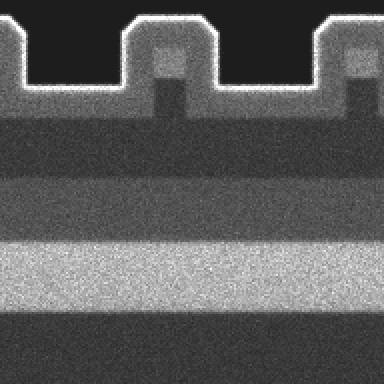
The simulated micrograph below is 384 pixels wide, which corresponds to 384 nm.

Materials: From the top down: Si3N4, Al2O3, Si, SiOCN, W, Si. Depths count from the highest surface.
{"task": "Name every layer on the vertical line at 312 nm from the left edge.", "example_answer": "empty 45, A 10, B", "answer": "empty 70, Si3N4 32, Si 60, SiOCN 64, W 70, Si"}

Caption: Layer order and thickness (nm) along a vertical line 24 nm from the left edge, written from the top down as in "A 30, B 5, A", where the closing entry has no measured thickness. empty 16, Si3N4 86, Si 60, SiOCN 64, W 70, Si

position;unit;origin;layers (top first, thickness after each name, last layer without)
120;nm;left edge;empty 70, Si3N4 32, Si 60, SiOCN 64, W 70, Si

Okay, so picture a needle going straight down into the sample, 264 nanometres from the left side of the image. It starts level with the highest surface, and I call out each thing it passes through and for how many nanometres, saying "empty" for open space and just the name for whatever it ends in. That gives empty 70, Si3N4 32, Si 60, SiOCN 64, W 70, Si